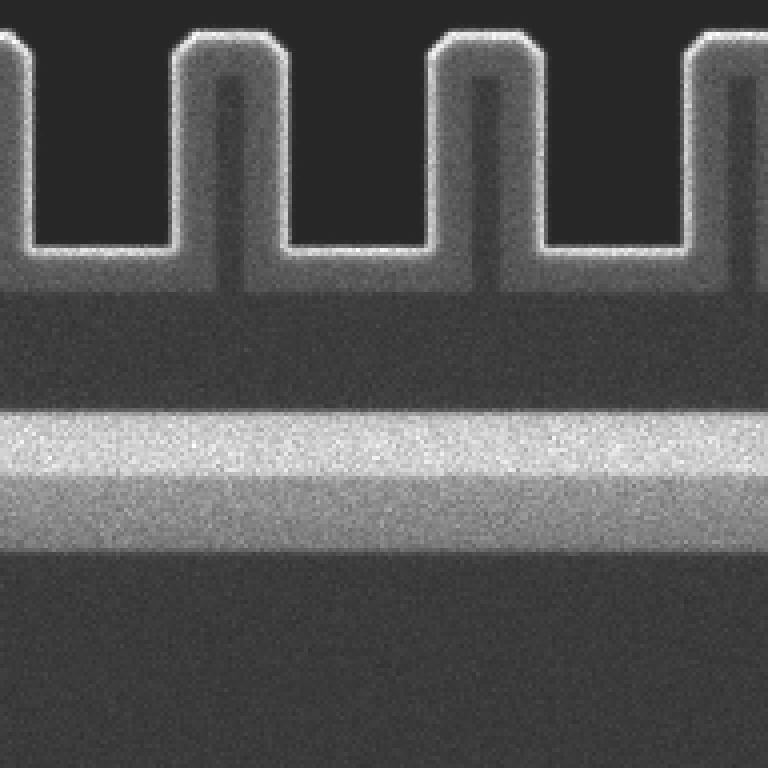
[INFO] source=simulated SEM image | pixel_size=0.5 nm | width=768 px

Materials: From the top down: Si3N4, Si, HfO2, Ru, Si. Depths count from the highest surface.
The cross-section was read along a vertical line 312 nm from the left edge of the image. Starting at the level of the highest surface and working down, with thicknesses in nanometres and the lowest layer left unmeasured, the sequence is empty 108, Si3N4 22, Si 60, HfO2 32, Ru 38, Si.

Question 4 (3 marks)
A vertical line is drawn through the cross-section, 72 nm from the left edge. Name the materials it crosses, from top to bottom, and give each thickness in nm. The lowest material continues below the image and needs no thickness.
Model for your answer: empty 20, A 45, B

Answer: empty 108, Si3N4 22, Si 60, HfO2 32, Ru 38, Si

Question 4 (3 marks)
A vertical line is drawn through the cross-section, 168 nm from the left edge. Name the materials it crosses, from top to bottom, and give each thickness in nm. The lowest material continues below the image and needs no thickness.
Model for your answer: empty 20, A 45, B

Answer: empty 108, Si3N4 22, Si 60, HfO2 32, Ru 38, Si